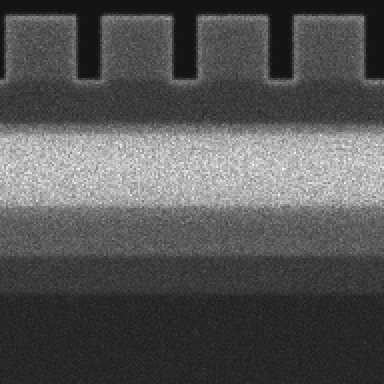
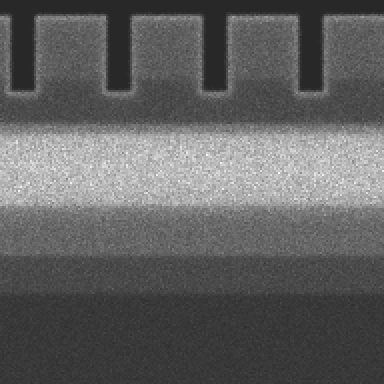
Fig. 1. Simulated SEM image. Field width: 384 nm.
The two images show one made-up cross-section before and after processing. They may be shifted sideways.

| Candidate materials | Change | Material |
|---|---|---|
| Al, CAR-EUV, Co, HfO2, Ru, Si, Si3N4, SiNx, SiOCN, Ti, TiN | removed | SiNx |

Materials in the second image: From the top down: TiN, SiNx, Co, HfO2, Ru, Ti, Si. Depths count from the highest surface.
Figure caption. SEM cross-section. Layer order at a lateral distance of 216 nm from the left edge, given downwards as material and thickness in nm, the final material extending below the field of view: empty 76, SiNx 32, Co 10, HfO2 72, Ru 50, Ti 38, Si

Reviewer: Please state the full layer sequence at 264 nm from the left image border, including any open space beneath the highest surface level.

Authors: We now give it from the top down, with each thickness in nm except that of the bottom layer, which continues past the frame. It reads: TiN 64, SiNx 44, Co 10, HfO2 72, Ru 50, Ti 38, Si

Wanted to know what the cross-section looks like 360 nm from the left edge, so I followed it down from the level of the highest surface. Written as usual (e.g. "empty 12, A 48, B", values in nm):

TiN 64, SiNx 44, Co 10, HfO2 72, Ru 50, Ti 38, Si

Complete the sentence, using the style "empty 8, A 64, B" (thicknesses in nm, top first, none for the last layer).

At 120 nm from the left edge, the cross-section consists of empty 76, SiNx 32, Co 10, HfO2 72, Ru 50, Ti 38, Si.